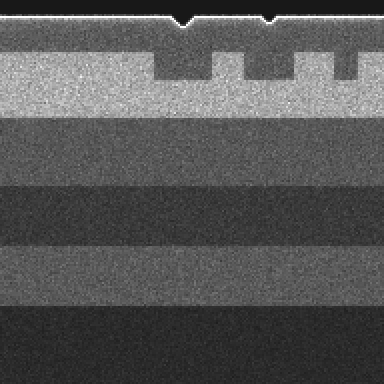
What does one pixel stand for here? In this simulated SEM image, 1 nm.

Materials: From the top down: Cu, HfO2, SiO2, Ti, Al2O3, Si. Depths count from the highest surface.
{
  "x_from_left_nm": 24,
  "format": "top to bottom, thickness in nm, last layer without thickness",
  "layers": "Cu 36, HfO2 66, SiO2 68, Ti 60, Al2O3 60, Si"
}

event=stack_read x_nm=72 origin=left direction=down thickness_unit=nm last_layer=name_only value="Cu 36, HfO2 66, SiO2 68, Ti 60, Al2O3 60, Si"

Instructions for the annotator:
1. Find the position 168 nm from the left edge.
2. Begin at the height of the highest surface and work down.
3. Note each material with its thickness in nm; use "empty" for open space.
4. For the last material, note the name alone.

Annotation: Cu 64, HfO2 38, SiO2 68, Ti 60, Al2O3 60, Si